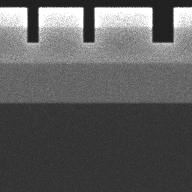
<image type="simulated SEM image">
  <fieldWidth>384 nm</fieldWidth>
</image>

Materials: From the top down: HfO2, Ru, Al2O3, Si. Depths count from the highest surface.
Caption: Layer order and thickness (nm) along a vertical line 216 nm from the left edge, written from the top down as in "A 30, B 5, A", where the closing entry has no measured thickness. HfO2 38, Ru 72, Al2O3 80, Si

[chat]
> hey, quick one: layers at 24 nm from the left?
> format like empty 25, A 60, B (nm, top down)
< HfO2 38, Ru 72, Al2O3 80, Si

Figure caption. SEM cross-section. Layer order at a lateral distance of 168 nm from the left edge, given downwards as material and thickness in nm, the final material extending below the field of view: empty 70, Ru 40, Al2O3 80, Si